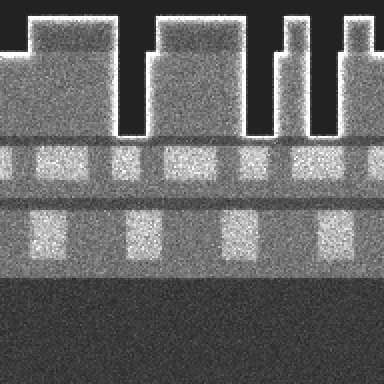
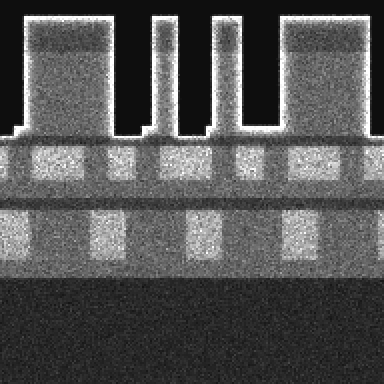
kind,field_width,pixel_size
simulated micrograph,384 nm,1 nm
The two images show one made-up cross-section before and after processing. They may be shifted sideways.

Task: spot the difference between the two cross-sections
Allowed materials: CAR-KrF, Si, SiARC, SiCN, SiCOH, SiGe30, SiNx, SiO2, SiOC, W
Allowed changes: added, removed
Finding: removed SiO2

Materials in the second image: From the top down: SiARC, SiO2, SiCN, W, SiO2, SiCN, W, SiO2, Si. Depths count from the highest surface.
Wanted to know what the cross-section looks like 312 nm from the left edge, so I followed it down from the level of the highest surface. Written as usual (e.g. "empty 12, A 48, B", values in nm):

SiARC 36, SiO2 84, SiCN 10, W 34, SiO2 18, SiCN 12, W 50, SiO2 18, Si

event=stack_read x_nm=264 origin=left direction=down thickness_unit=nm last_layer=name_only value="empty 110, SiO2 10, SiCN 10, SiO2 52, SiCN 12, SiO2 68, Si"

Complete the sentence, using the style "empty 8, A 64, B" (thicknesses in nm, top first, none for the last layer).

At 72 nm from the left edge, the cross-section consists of SiARC 36, SiO2 84, SiCN 10, W 34, SiO2 18, SiCN 12, SiO2 68, Si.